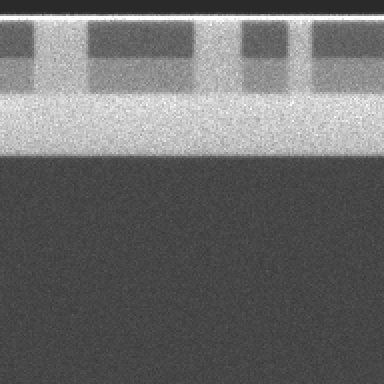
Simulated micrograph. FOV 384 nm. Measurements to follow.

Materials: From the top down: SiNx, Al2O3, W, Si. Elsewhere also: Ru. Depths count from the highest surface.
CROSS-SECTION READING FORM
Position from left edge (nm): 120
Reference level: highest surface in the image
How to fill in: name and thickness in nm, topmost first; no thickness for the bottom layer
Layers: SiNx 42, Al2O3 36, W 62, Si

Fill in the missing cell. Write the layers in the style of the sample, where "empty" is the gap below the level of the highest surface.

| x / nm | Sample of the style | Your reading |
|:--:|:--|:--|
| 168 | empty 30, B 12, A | SiNx 42, Al2O3 36, W 62, Si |